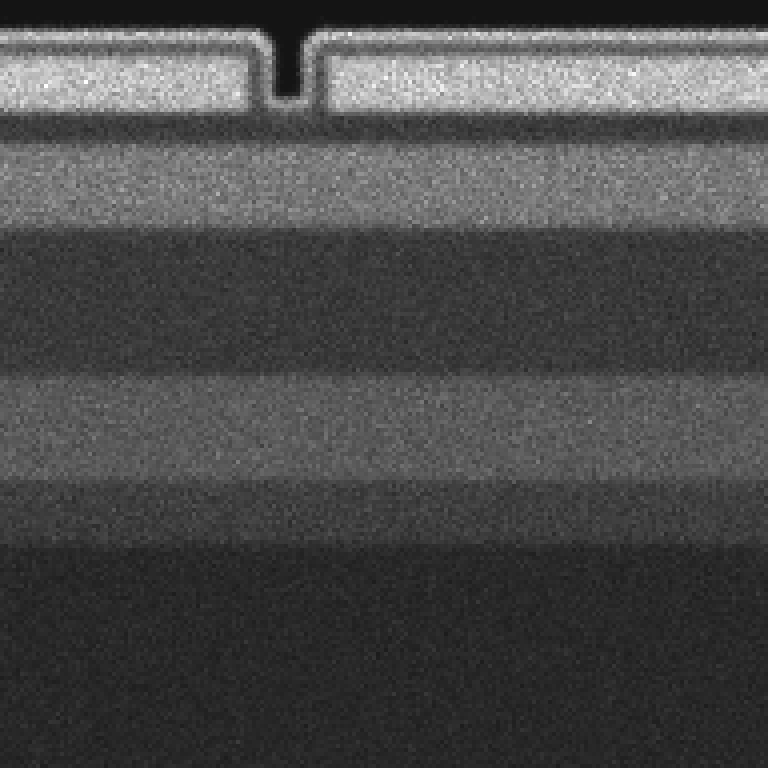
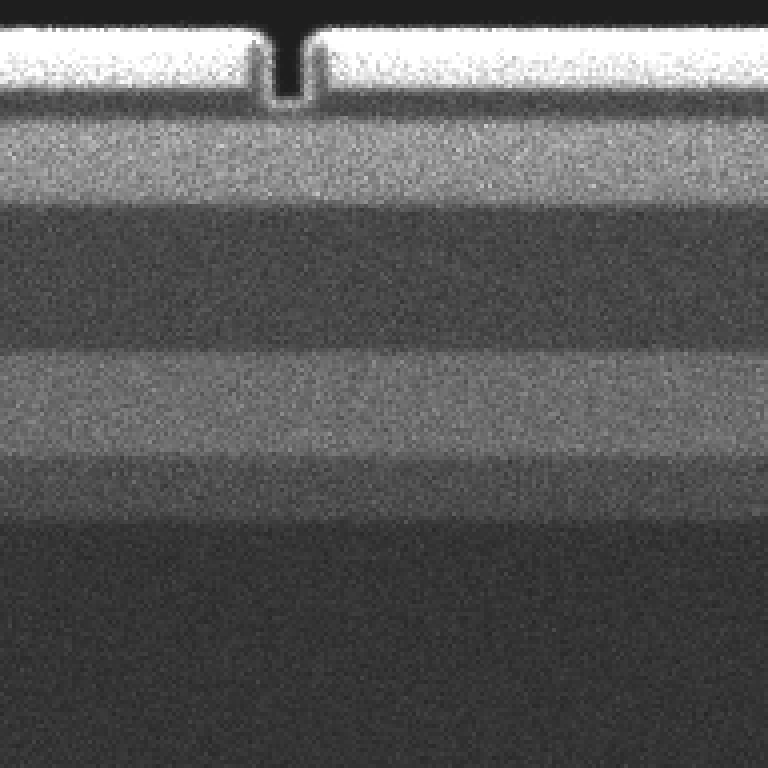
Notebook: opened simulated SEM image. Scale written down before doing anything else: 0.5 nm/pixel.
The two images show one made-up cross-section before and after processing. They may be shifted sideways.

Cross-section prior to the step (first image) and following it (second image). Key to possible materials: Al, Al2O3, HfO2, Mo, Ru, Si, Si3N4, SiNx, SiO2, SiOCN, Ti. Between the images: Si3N4 was removed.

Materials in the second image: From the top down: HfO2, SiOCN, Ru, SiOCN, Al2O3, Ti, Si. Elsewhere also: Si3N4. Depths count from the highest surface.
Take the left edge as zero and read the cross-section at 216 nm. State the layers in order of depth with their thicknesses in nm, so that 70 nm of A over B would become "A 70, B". HfO2 28, SiOCN 16, Ru 42, SiOCN 74, Al2O3 52, Ti 32, Si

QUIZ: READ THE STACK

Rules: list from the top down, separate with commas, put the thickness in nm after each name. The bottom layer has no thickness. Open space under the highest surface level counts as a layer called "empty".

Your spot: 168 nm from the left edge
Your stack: HfO2 28, SiOCN 16, Ru 42, SiOCN 74, Al2O3 52, Ti 32, Si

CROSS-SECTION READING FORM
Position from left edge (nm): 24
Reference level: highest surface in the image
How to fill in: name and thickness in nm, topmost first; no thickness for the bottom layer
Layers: HfO2 28, SiOCN 16, Ru 42, SiOCN 74, Al2O3 52, Ti 32, Si